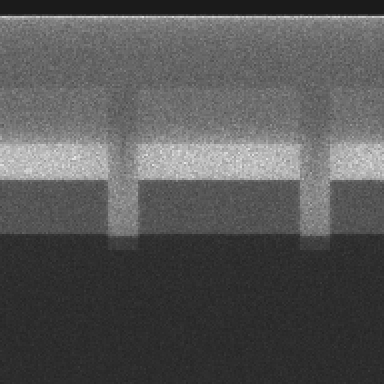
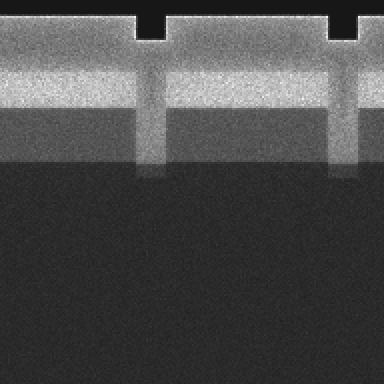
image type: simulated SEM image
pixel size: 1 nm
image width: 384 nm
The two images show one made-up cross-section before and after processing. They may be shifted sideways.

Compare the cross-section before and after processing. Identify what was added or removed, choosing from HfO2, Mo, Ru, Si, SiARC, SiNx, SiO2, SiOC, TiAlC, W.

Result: Ru removed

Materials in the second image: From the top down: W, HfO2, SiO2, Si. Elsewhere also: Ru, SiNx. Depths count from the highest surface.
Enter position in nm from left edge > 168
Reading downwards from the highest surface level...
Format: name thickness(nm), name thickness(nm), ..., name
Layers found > W 56, HfO2 36, SiO2 54, Si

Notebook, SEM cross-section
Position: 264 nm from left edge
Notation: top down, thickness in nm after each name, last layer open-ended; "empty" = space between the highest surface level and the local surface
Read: W 56, HfO2 36, SiO2 54, Si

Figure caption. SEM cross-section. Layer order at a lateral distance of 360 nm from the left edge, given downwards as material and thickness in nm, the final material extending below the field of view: W 56, HfO2 36, SiO2 54, Si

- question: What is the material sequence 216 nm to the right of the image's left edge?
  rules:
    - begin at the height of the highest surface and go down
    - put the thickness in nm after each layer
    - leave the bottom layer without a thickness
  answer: W 56, HfO2 36, SiO2 54, Si